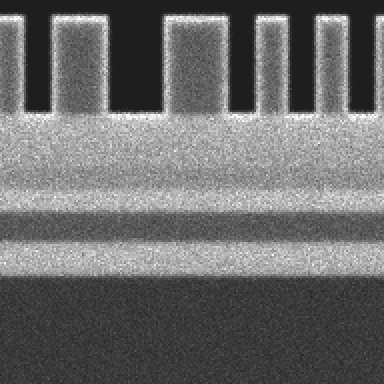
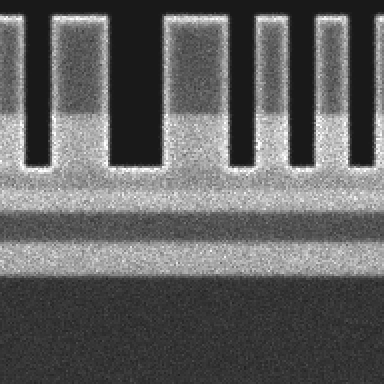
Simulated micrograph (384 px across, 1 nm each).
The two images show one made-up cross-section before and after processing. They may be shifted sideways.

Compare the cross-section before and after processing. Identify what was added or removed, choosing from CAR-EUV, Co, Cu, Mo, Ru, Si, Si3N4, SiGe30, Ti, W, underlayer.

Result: Ru removed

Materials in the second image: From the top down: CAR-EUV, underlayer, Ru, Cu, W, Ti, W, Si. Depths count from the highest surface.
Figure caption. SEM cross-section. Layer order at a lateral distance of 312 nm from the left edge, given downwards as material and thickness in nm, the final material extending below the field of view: empty 152, Cu 22, W 22, Ti 30, W 34, Si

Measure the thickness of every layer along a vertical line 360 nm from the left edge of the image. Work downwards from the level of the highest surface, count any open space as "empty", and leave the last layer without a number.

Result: empty 152, Cu 22, W 22, Ti 30, W 34, Si